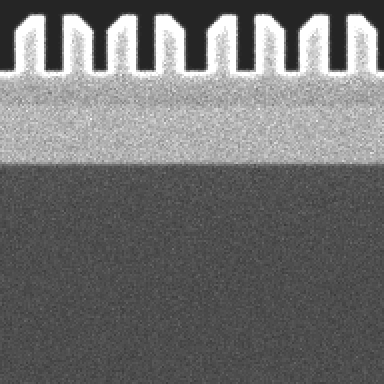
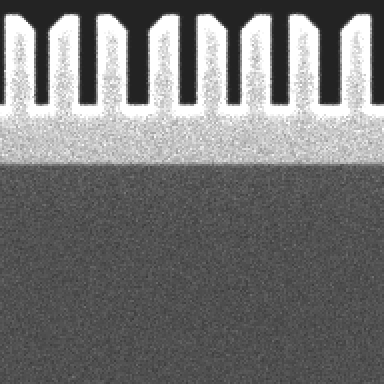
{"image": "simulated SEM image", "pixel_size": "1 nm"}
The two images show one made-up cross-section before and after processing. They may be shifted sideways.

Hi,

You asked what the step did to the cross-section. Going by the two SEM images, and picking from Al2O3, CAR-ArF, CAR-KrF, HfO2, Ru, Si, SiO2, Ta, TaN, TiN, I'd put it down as TiN, removed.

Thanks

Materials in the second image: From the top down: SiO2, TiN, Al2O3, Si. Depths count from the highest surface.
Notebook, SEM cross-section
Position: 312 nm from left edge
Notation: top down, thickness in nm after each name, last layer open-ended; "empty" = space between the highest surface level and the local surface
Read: empty 10, SiO2 46, TiN 34, Al2O3 58, Si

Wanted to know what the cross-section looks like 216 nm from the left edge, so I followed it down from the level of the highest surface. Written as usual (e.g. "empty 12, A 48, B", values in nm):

empty 6, SiO2 50, TiN 34, Al2O3 58, Si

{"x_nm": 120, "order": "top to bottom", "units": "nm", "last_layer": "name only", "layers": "empty 10, SiO2 46, TiN 34, Al2O3 58, Si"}